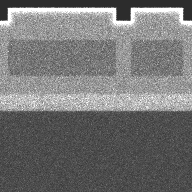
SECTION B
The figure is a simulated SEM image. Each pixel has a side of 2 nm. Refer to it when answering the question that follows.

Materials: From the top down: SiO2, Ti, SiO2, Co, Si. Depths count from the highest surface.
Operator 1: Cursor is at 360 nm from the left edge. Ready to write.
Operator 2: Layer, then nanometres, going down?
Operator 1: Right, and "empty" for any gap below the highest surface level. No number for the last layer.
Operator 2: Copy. SiO2 64, Ti 72, SiO2 36, Co 34, Si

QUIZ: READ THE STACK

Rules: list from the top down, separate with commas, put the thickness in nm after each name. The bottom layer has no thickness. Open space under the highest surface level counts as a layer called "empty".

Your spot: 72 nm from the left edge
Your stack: SiO2 64, Ti 72, SiO2 36, Co 34, Si